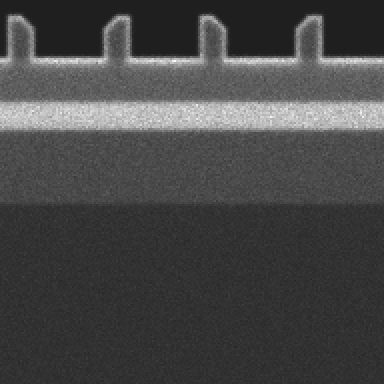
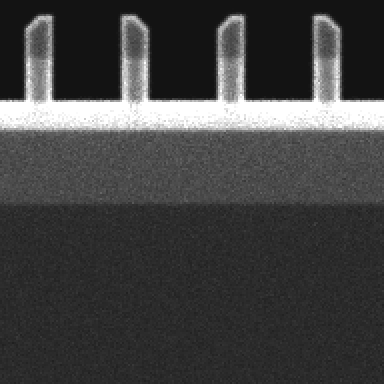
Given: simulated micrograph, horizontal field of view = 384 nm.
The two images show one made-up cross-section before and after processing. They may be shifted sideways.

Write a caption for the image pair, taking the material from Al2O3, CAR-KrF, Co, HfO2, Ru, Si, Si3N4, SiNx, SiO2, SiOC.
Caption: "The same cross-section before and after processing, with SiO2 removed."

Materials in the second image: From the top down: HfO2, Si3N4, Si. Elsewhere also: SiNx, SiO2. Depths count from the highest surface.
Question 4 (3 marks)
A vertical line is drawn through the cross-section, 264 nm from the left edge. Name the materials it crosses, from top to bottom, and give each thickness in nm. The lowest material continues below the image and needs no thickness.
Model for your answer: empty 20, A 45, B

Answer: empty 86, HfO2 28, Si3N4 74, Si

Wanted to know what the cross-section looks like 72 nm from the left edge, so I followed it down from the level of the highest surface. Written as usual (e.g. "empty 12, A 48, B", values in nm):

empty 86, HfO2 28, Si3N4 74, Si